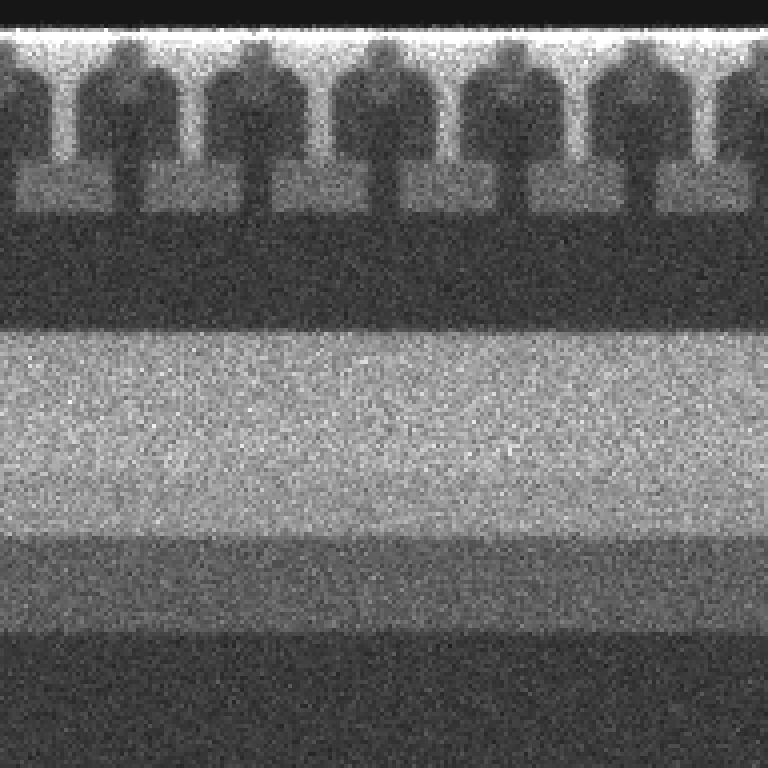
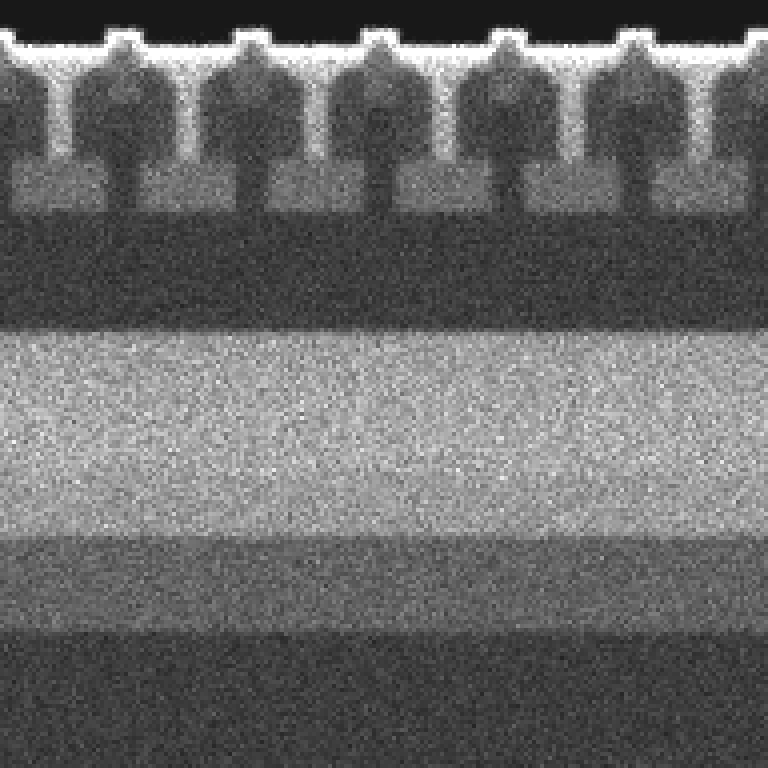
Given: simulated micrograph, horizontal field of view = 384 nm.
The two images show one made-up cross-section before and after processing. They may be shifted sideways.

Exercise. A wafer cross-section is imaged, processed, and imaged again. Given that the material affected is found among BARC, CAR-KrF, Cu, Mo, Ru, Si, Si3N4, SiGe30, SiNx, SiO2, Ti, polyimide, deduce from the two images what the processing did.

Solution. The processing removed Ru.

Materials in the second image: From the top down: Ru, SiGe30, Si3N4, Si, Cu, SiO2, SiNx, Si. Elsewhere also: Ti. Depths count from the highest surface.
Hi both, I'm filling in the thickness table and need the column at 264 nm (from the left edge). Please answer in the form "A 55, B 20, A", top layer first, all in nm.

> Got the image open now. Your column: empty 8, Ru 10, SiGe30 46, Si3N4 26, Si 60, Cu 72, SiO2 30, SiNx 48, Si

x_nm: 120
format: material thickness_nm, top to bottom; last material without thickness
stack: Ti 36, Si 114, Cu 72, SiO2 30, SiNx 48, Si